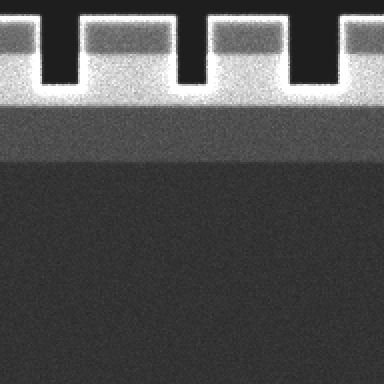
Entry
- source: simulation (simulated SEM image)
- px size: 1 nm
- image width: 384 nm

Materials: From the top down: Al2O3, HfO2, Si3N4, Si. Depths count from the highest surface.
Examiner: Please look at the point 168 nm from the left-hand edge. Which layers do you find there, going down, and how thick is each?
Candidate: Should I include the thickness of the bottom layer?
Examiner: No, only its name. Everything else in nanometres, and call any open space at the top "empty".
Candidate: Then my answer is Al2O3 38, HfO2 52, Si3N4 56, Si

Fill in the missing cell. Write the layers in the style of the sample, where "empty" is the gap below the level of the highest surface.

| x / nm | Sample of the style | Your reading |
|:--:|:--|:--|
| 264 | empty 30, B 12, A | Al2O3 38, HfO2 52, Si3N4 56, Si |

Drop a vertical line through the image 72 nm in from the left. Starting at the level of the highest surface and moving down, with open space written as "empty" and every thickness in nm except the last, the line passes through empty 70, HfO2 20, Si3N4 56, Si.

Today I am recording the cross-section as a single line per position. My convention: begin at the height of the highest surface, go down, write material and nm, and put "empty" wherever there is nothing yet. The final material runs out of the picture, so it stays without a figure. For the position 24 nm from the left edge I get Al2O3 38, HfO2 52, Si3N4 56, Si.